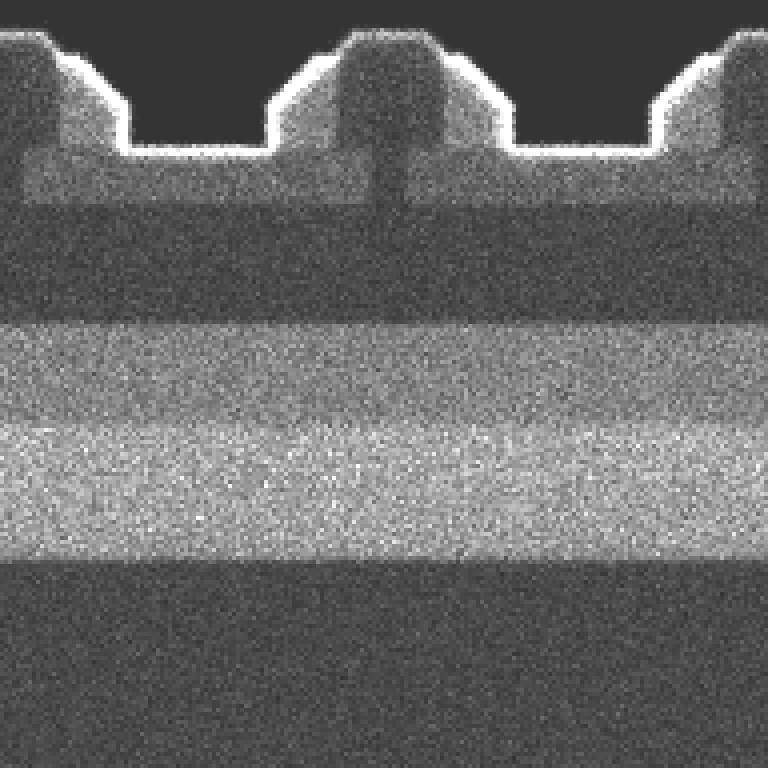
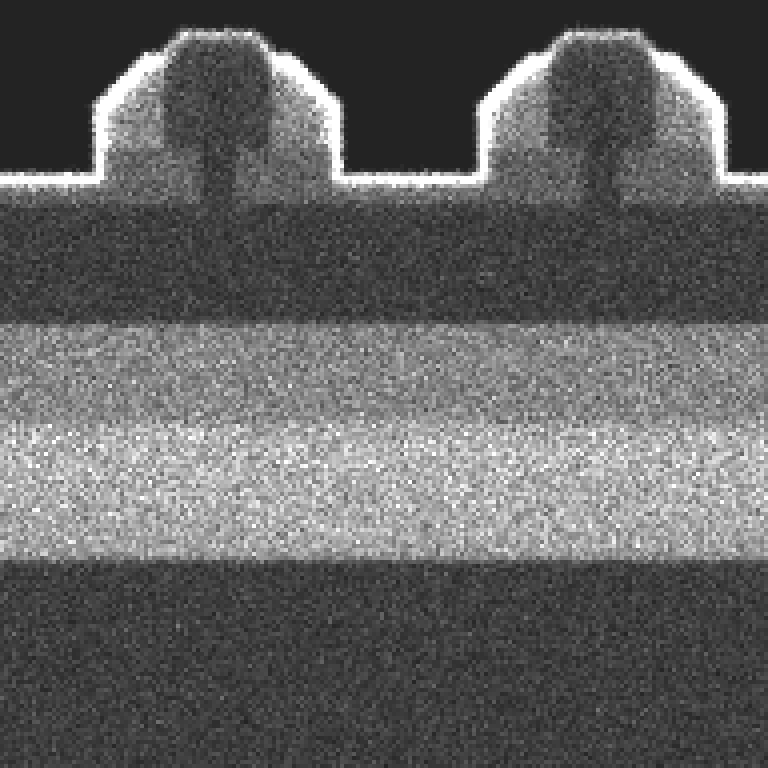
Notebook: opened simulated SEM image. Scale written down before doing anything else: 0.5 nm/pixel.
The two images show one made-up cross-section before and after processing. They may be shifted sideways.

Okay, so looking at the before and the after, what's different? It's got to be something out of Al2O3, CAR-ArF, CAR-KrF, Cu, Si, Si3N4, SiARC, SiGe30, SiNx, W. Si3N4, removed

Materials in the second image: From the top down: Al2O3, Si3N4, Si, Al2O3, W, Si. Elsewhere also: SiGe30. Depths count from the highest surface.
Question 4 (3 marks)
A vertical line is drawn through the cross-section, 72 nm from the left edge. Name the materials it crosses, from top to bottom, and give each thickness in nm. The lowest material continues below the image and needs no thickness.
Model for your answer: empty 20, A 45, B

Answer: empty 12, Al2O3 46, Si3N4 28, Si 60, Al2O3 50, W 68, Si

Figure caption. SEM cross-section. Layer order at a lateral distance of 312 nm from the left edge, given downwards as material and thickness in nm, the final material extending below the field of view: SiGe30 58, Si3N4 28, Si 60, Al2O3 50, W 68, Si